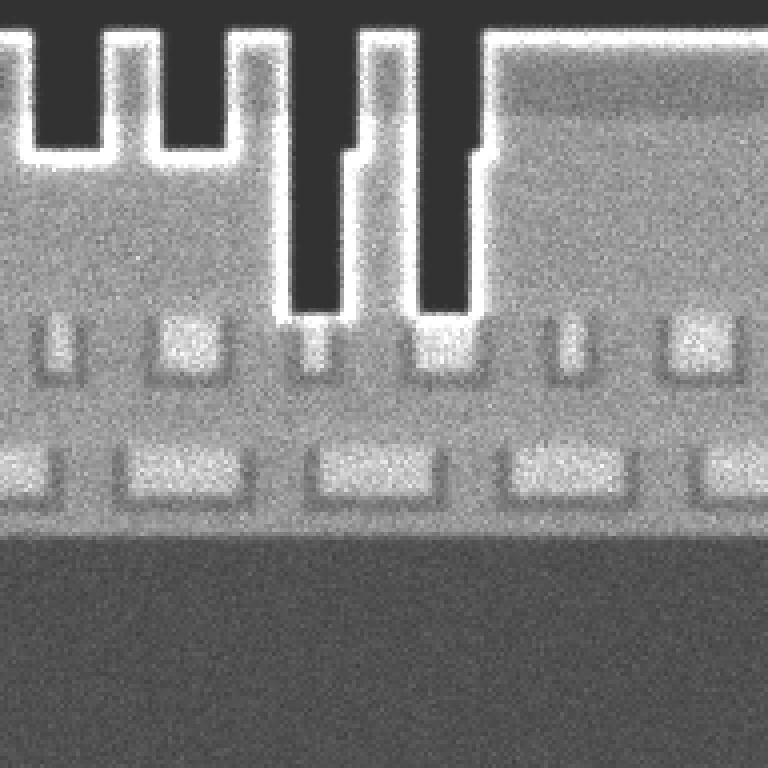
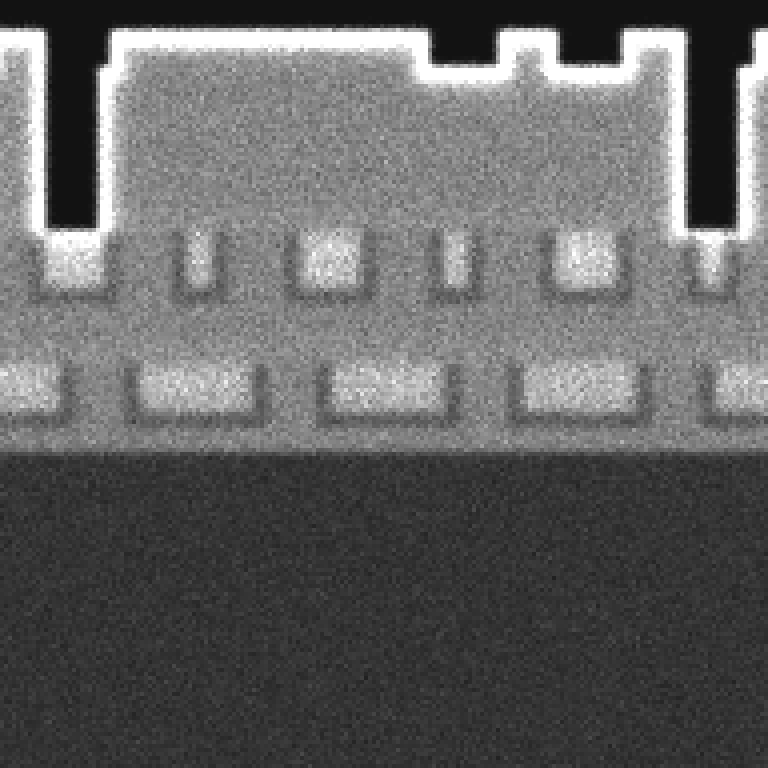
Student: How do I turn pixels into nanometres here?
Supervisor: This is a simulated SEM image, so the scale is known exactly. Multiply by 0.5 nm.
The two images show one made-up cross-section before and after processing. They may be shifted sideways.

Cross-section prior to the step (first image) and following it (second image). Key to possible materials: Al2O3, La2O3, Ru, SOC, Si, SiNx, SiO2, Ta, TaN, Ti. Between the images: SOC was removed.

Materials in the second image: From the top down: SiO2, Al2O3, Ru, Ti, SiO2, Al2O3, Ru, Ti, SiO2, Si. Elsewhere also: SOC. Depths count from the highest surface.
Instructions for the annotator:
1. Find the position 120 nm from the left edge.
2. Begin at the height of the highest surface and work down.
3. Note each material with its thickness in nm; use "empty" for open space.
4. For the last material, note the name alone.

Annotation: SiO2 88, Al2O3 12, SiO2 52, Al2O3 14, Ru 24, Ti 8, SiO2 12, Si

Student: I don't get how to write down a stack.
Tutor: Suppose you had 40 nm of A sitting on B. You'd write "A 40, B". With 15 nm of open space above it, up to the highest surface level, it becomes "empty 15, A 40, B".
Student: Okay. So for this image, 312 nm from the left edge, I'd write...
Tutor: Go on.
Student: SiO2 88, Al2O3 12, Ti 36, SiO2 16, Al2O3 14, Ru 24, Ti 8, SiO2 12, Si